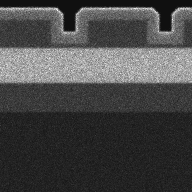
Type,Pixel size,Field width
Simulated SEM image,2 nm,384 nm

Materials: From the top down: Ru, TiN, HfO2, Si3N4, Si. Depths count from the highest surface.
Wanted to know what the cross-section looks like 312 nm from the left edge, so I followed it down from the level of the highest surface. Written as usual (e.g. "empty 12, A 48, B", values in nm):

empty 8, Ru 64, TiN 8, HfO2 70, Si3N4 58, Si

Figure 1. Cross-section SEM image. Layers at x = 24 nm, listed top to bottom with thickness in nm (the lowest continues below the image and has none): Ru 24, TiN 56, HfO2 70, Si3N4 58, Si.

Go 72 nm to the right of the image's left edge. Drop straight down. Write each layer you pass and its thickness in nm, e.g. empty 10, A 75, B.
Ru 24, TiN 56, HfO2 70, Si3N4 58, Si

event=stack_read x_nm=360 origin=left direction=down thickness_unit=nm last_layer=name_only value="Ru 72, TiN 8, HfO2 70, Si3N4 58, Si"